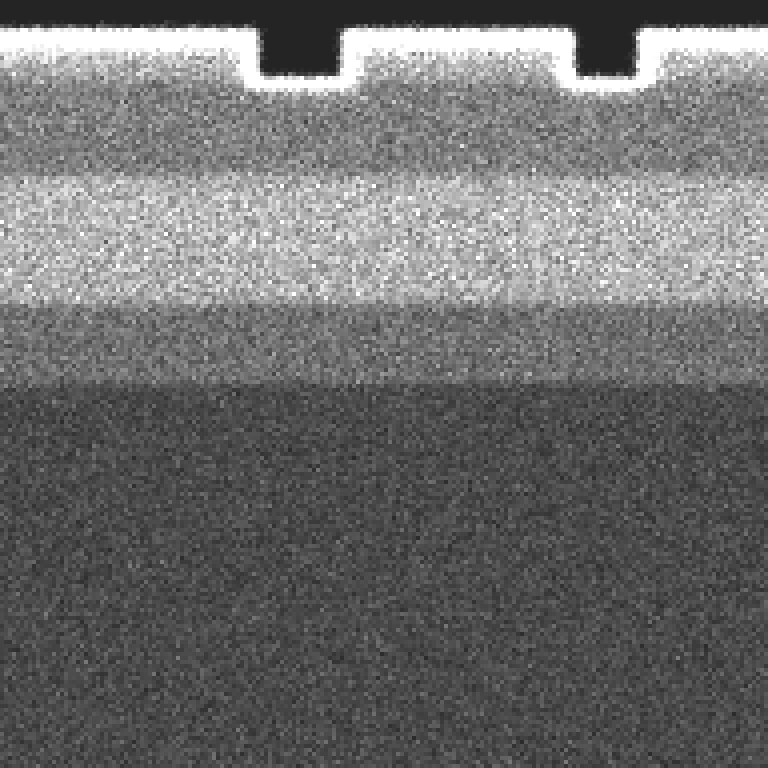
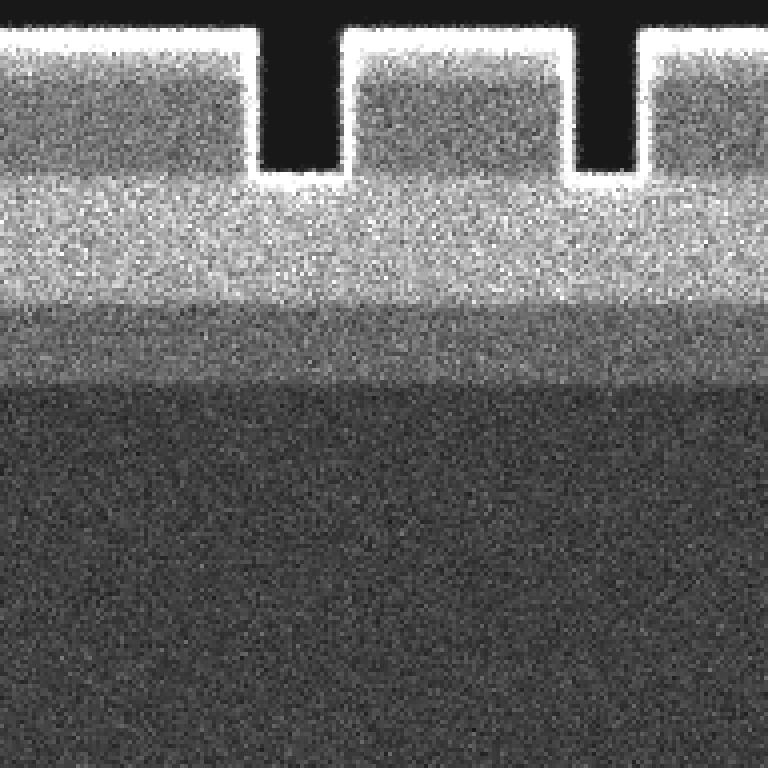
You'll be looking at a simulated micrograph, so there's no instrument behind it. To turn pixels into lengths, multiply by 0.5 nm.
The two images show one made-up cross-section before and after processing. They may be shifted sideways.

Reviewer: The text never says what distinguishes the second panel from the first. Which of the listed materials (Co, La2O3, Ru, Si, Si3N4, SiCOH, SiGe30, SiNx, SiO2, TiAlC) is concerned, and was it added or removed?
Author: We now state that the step removed Si3N4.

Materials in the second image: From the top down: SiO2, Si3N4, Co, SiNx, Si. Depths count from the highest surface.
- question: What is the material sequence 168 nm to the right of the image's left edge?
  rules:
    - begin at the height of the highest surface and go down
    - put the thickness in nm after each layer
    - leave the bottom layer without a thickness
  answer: empty 72, Co 64, SiNx 40, Si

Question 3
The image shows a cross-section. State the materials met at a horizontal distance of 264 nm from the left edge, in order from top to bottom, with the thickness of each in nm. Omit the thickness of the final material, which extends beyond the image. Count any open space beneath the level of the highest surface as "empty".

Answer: SiO2 24, Si3N4 48, Co 64, SiNx 40, Si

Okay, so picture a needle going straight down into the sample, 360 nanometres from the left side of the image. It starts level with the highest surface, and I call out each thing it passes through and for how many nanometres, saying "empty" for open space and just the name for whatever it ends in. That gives SiO2 24, Si3N4 48, Co 64, SiNx 40, Si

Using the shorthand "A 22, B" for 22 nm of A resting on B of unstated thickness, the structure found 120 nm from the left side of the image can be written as SiO2 24, Si3N4 48, Co 64, SiNx 40, Si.